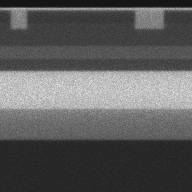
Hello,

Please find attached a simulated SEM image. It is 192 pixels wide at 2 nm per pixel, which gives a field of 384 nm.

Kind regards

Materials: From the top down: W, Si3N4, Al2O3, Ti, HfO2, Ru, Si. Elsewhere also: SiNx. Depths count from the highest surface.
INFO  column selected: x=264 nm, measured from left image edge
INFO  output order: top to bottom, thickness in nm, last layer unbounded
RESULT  SiNx 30, Si3N4 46, Al2O3 26, Ti 24, HfO2 76, Ru 62, Si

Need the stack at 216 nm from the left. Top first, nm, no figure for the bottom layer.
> SiNx 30, Si3N4 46, Al2O3 26, Ti 24, HfO2 76, Ru 62, Si